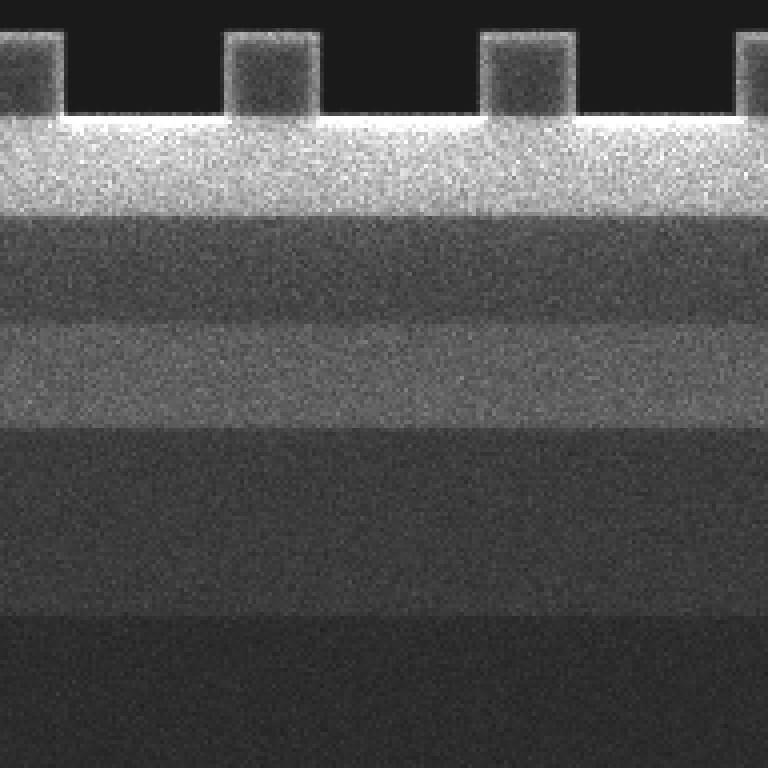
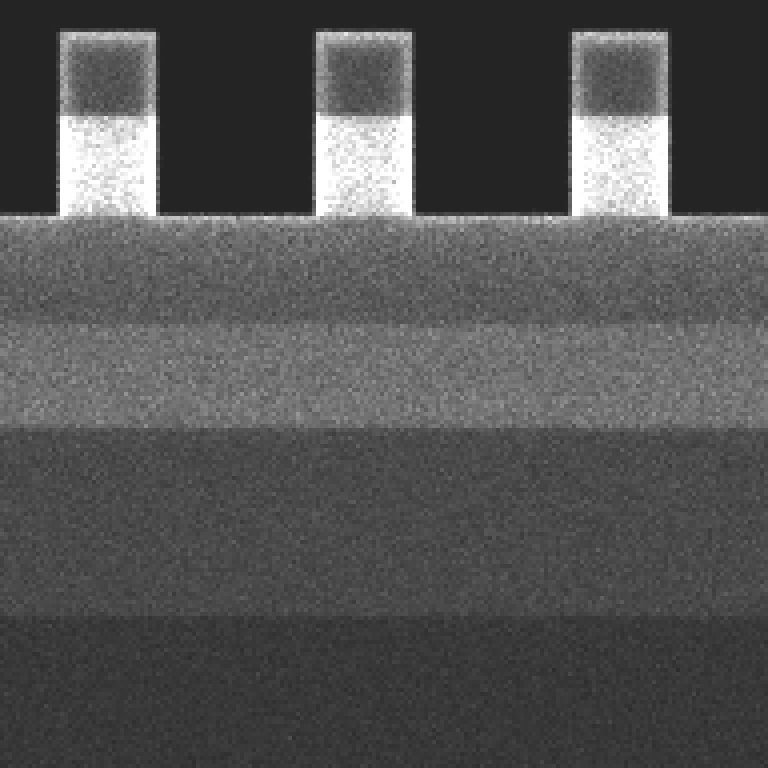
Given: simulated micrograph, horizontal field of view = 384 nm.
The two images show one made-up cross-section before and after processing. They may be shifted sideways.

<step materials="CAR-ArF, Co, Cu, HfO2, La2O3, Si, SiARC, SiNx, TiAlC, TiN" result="removed HfO2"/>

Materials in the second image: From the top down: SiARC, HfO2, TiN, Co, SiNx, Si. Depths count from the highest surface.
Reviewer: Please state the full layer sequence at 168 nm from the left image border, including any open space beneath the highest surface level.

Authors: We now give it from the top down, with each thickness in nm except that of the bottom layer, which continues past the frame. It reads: SiARC 42, HfO2 50, TiN 54, Co 52, SiNx 94, Si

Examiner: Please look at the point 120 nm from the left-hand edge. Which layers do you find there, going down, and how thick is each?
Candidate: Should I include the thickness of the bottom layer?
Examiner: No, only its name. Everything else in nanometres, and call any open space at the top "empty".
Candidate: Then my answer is empty 92, TiN 54, Co 52, SiNx 94, Si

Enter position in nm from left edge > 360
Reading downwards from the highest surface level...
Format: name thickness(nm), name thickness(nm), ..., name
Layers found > empty 92, TiN 54, Co 52, SiNx 94, Si